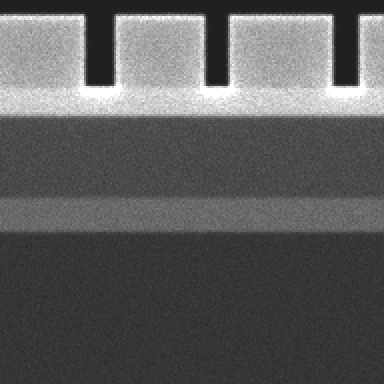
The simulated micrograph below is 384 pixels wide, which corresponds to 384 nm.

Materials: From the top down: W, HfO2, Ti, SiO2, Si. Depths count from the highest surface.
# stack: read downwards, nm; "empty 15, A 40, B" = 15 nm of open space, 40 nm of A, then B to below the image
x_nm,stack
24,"W 72, HfO2 28, Ti 82, SiO2 34, Si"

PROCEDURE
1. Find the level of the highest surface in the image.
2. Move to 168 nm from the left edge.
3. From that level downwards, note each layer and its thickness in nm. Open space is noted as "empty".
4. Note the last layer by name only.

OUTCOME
W 72, HfO2 28, Ti 82, SiO2 34, Si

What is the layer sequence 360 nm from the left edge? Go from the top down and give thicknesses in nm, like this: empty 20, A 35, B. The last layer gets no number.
W 72, HfO2 28, Ti 82, SiO2 34, Si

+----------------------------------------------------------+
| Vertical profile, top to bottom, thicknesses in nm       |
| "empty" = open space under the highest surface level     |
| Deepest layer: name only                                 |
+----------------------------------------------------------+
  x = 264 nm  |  W 72, HfO2 28, Ti 82, SiO2 34, Si